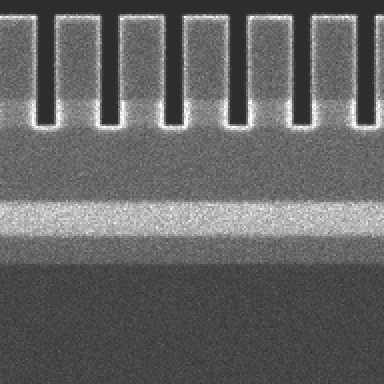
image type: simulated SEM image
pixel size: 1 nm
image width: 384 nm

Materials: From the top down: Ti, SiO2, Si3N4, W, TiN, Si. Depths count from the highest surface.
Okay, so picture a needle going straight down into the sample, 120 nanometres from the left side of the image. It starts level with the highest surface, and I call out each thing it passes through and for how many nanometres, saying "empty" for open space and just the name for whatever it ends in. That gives Ti 84, SiO2 26, Si3N4 76, W 34, TiN 28, Si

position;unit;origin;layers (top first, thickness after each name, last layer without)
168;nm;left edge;empty 110, Si3N4 76, W 34, TiN 28, Si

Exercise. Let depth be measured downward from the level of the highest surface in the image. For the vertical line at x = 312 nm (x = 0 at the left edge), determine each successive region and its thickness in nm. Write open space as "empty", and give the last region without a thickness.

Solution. Ti 84, SiO2 26, Si3N4 76, W 34, TiN 28, Si